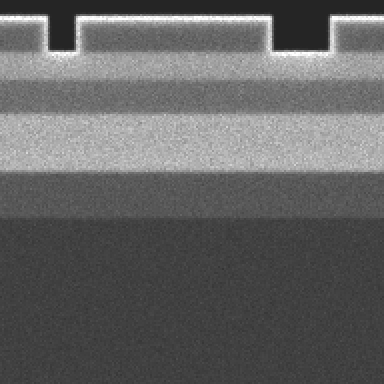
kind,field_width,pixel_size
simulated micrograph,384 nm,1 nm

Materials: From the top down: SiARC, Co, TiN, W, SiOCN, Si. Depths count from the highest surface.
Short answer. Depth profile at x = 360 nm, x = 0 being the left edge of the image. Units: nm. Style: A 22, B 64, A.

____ SiARC 36, Co 28, TiN 34, W 58, SiOCN 46, Si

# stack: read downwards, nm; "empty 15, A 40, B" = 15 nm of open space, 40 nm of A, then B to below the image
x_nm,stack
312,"empty 36, Co 28, TiN 34, W 58, SiOCN 46, Si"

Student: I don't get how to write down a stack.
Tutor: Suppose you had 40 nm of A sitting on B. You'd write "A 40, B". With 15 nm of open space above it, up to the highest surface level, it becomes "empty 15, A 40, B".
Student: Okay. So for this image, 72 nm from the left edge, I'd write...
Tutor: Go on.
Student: empty 36, Co 28, TiN 34, W 58, SiOCN 46, Si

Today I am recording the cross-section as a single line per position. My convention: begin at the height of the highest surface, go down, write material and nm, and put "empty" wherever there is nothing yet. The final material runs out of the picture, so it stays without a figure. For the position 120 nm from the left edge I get SiARC 36, Co 28, TiN 34, W 58, SiOCN 46, Si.